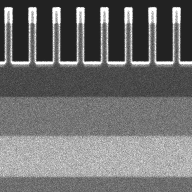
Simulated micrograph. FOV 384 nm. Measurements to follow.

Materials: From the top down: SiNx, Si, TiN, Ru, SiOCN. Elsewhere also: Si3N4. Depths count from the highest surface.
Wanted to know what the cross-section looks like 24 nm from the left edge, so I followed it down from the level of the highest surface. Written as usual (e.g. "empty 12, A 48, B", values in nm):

empty 108, SiNx 10, Si 60, TiN 78, Ru 82, SiOCN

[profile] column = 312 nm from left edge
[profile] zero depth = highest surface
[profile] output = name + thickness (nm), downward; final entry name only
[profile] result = empty 108, SiNx 10, Si 60, TiN 78, Ru 82, SiOCN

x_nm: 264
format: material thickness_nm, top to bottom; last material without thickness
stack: empty 108, SiNx 10, Si 60, TiN 78, Ru 82, SiOCN